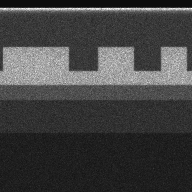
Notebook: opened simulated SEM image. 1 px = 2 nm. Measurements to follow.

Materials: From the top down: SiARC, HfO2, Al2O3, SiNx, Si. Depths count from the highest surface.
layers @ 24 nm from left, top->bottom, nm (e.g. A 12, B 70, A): SiARC 78, HfO2 76, Al2O3 30, SiNx 66, Si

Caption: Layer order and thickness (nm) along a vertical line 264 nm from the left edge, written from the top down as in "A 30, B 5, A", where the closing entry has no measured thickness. SiARC 78, HfO2 76, Al2O3 30, SiNx 66, Si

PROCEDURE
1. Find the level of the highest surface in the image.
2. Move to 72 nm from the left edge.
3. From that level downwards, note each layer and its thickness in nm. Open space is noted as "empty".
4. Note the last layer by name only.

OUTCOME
SiARC 78, HfO2 76, Al2O3 30, SiNx 66, Si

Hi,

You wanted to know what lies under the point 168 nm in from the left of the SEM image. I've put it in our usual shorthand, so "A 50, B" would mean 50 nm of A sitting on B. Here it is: SiARC 126, HfO2 28, Al2O3 30, SiNx 66, Si